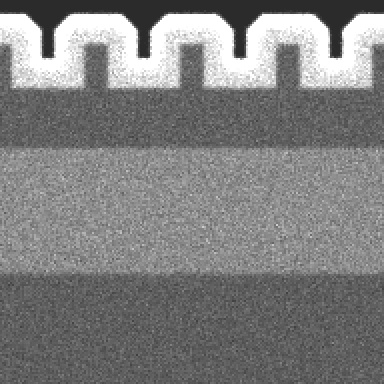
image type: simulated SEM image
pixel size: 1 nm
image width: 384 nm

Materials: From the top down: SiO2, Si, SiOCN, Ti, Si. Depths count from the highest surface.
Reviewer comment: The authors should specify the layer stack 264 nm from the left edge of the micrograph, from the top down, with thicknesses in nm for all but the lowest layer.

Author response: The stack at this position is SiO2 72, Si 60, SiOCN 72, Ti 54, Si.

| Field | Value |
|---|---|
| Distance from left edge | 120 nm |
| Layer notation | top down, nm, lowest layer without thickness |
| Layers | SiO2 72, Si 60, SiOCN 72, Ti 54, Si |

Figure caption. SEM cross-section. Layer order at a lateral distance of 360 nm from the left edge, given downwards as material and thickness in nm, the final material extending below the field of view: SiO2 72, Si 60, SiOCN 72, Ti 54, Si